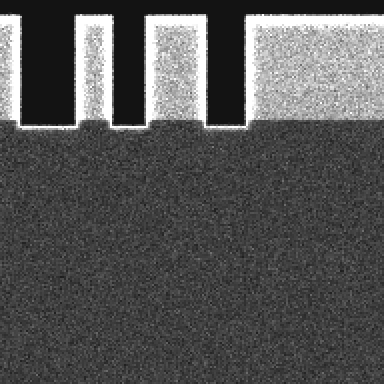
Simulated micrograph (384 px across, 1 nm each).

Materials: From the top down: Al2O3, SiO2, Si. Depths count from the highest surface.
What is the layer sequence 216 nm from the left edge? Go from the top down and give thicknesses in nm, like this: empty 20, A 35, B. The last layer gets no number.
empty 110, Si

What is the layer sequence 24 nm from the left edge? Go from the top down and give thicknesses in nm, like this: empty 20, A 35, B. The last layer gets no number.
empty 110, Si